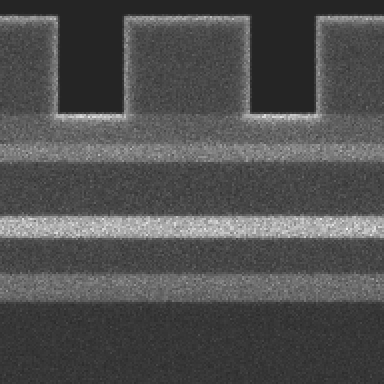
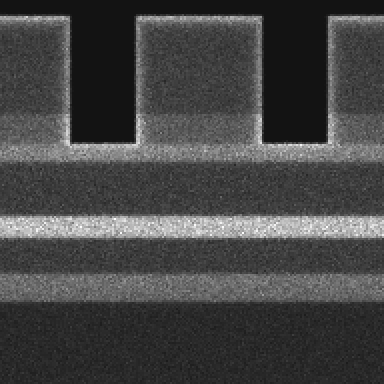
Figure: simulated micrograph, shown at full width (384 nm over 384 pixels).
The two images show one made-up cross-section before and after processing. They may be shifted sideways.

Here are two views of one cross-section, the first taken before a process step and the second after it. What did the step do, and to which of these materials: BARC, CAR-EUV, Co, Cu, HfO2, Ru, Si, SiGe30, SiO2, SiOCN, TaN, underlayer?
It removed SiO2.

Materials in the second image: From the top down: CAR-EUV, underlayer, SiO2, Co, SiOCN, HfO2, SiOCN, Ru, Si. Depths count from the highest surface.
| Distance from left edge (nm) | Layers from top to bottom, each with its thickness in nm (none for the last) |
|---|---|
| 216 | CAR-EUV 46, underlayer 52, SiO2 30, Co 18, SiOCN 54, HfO2 22, SiOCN 36, Ru 28, Si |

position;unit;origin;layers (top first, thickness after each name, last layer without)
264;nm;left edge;empty 128, Co 18, SiOCN 54, HfO2 22, SiOCN 36, Ru 28, Si